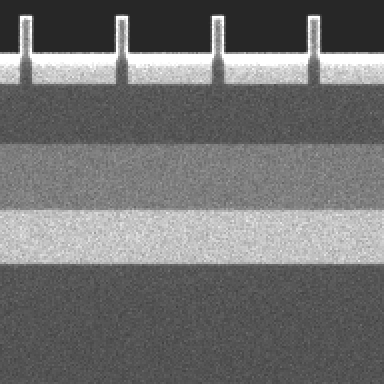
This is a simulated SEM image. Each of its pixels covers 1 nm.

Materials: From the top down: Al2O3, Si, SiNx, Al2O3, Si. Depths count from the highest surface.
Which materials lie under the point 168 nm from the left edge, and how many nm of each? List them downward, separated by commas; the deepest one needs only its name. empty 38, Al2O3 30, Si 60, SiNx 66, Al2O3 54, Si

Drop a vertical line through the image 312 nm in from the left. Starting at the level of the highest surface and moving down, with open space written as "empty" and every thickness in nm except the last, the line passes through Si 128, SiNx 66, Al2O3 54, Si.